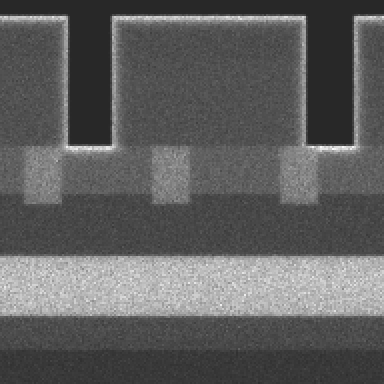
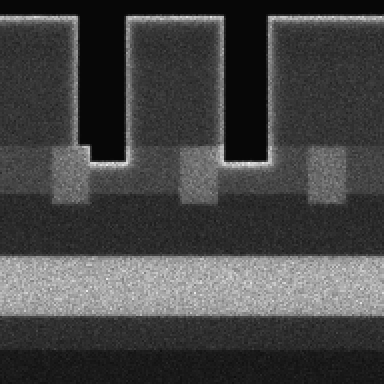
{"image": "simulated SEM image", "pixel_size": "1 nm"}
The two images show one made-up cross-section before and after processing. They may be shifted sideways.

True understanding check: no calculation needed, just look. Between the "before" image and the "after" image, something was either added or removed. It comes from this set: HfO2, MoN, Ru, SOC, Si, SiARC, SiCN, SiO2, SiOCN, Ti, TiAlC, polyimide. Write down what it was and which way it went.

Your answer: SiO2 (removed)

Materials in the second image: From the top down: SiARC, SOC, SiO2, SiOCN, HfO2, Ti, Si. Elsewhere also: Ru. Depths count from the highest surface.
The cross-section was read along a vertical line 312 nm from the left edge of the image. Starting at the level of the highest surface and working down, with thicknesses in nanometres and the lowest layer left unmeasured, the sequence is SiARC 44, SOC 86, Ru 58, SiOCN 52, HfO2 60, Ti 34, Si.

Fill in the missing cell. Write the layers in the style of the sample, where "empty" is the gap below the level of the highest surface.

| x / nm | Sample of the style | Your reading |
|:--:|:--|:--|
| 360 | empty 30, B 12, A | SiARC 44, SOC 86, SiO2 48, SiOCN 62, HfO2 60, Ti 34, Si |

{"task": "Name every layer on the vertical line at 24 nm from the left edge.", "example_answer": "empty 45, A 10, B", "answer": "SiARC 44, SOC 86, SiO2 48, SiOCN 62, HfO2 60, Ti 34, Si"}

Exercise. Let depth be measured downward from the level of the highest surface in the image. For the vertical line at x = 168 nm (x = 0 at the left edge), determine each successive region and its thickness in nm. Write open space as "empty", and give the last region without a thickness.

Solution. SiARC 44, SOC 86, SiO2 48, SiOCN 62, HfO2 60, Ti 34, Si